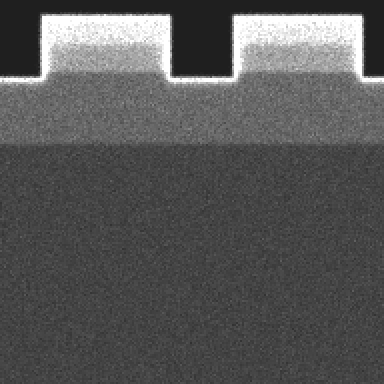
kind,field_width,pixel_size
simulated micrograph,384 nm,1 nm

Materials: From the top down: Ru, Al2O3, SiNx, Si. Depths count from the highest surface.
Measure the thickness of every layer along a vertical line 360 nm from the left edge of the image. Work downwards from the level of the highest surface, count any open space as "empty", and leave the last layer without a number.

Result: Ru 28, Al2O3 28, SiNx 72, Si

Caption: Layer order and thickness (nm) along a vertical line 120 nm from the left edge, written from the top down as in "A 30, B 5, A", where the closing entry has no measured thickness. Ru 28, Al2O3 28, SiNx 72, Si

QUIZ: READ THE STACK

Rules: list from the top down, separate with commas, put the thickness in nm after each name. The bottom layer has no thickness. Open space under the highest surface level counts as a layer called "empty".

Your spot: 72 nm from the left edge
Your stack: Ru 28, Al2O3 28, SiNx 72, Si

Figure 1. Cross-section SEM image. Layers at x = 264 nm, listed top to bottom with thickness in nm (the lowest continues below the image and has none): Ru 28, Al2O3 28, SiNx 72, Si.